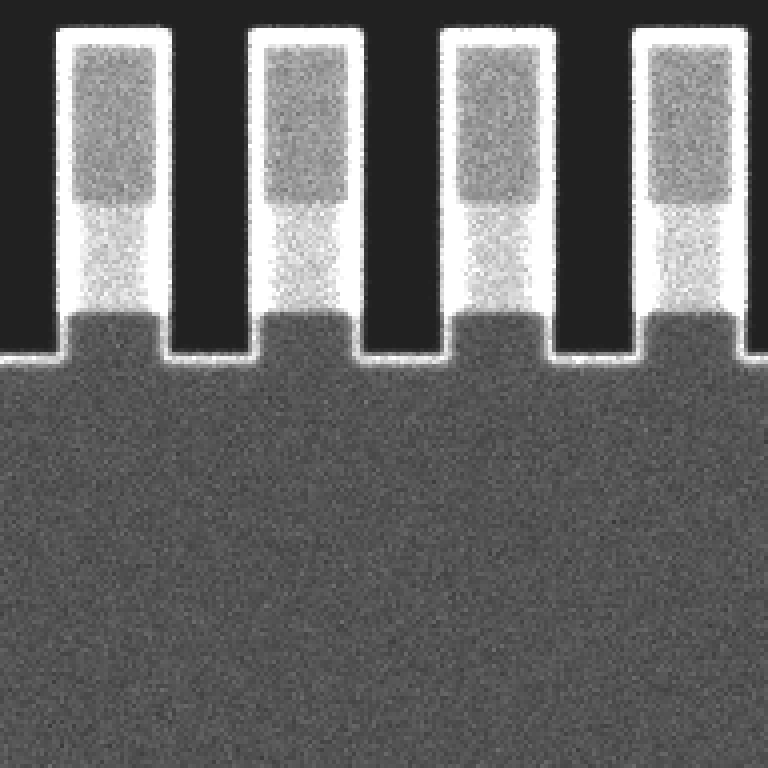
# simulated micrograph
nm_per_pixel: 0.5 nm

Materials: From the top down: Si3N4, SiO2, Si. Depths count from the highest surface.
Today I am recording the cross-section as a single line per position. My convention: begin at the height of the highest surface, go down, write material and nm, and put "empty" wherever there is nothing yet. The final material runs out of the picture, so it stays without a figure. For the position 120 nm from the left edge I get empty 162, Si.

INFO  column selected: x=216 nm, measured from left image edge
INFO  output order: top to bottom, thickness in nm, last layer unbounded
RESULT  empty 162, Si